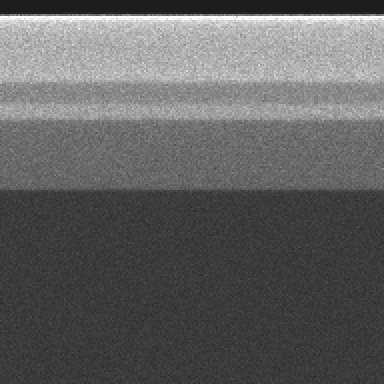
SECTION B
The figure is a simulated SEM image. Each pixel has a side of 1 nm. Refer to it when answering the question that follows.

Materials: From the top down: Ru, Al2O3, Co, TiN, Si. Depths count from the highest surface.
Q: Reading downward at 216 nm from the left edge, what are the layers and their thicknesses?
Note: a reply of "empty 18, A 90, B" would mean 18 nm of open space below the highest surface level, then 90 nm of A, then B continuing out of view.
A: Ru 66, Al2O3 22, Co 16, TiN 70, Si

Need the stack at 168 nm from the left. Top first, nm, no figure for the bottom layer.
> Ru 66, Al2O3 22, Co 16, TiN 70, Si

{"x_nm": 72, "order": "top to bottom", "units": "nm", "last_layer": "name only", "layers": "Ru 66, Al2O3 22, Co 16, TiN 70, Si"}